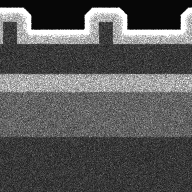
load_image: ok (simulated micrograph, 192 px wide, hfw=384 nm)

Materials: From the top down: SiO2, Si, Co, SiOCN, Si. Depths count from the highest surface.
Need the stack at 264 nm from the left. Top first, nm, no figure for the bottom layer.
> empty 44, SiO2 28, Si 60, Co 36, SiOCN 90, Si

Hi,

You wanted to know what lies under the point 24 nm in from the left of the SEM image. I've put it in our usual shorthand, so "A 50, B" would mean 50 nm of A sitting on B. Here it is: SiO2 28, Si 104, Co 36, SiOCN 90, Si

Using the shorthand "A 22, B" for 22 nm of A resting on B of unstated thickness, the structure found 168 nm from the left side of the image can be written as empty 44, SiO2 28, Si 60, Co 36, SiOCN 90, Si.